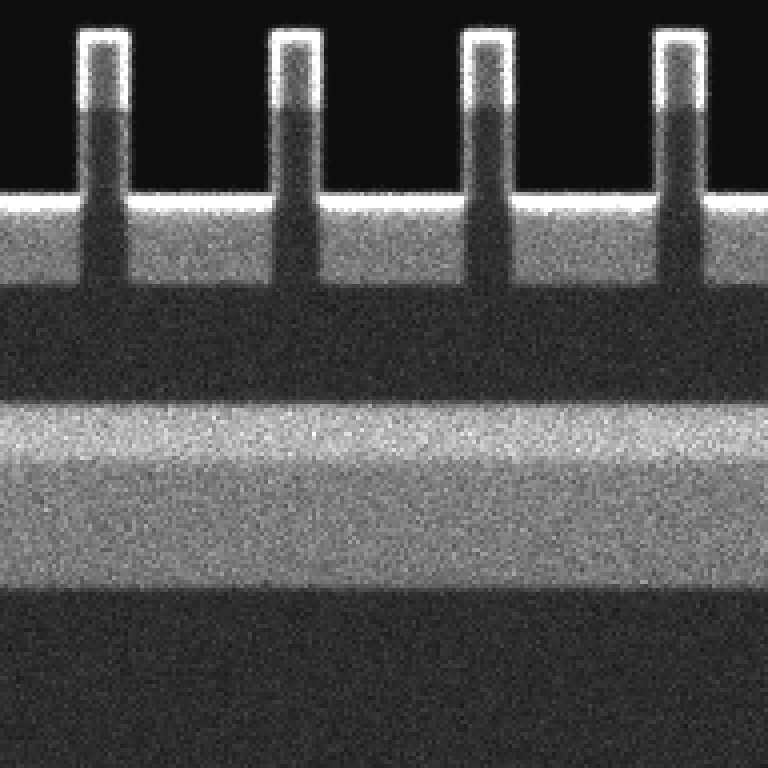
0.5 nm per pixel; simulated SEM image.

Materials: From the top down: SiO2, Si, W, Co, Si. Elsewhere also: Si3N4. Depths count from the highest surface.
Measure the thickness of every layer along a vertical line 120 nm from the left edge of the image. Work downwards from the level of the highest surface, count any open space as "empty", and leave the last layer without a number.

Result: empty 82, SiO2 44, Si 60, W 28, Co 64, Si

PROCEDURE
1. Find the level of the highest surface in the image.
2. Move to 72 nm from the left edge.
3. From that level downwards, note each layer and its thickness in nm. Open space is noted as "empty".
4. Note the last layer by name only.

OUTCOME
empty 82, SiO2 44, Si 60, W 28, Co 64, Si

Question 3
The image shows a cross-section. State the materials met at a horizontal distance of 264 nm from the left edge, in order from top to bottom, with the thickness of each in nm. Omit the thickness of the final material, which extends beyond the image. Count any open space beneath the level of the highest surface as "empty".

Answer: empty 82, SiO2 44, Si 60, W 28, Co 64, Si